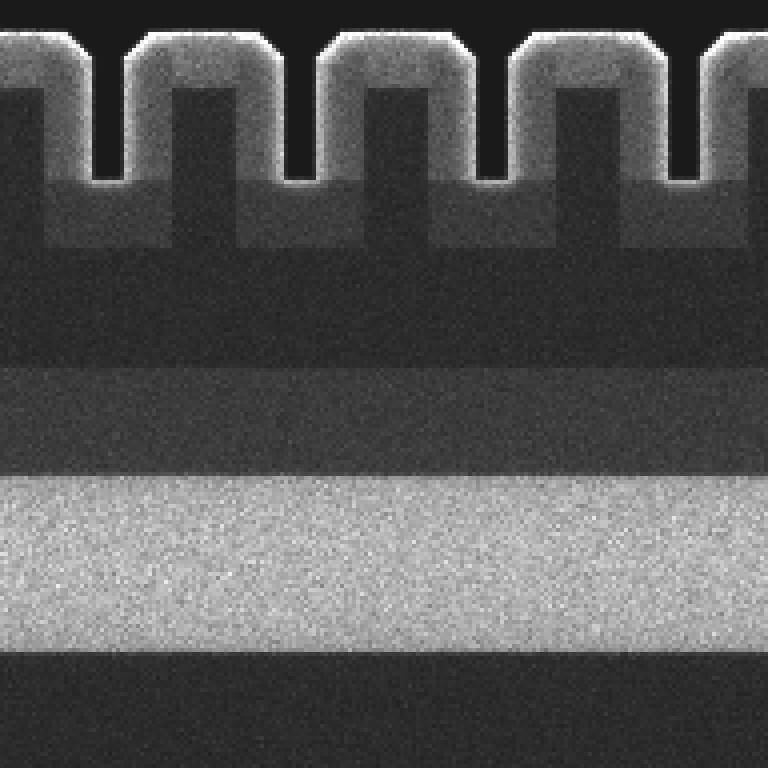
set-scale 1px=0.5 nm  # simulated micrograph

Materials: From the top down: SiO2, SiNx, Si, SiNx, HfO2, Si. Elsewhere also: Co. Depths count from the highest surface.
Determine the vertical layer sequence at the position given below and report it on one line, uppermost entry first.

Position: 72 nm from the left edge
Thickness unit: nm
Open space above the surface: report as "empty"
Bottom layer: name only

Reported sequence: empty 2, SiO2 72, SiNx 34, Si 60, SiNx 54, HfO2 88, Si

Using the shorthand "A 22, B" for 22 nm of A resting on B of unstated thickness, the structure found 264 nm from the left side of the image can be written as empty 2, SiO2 72, SiNx 34, Si 60, SiNx 54, HfO2 88, Si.